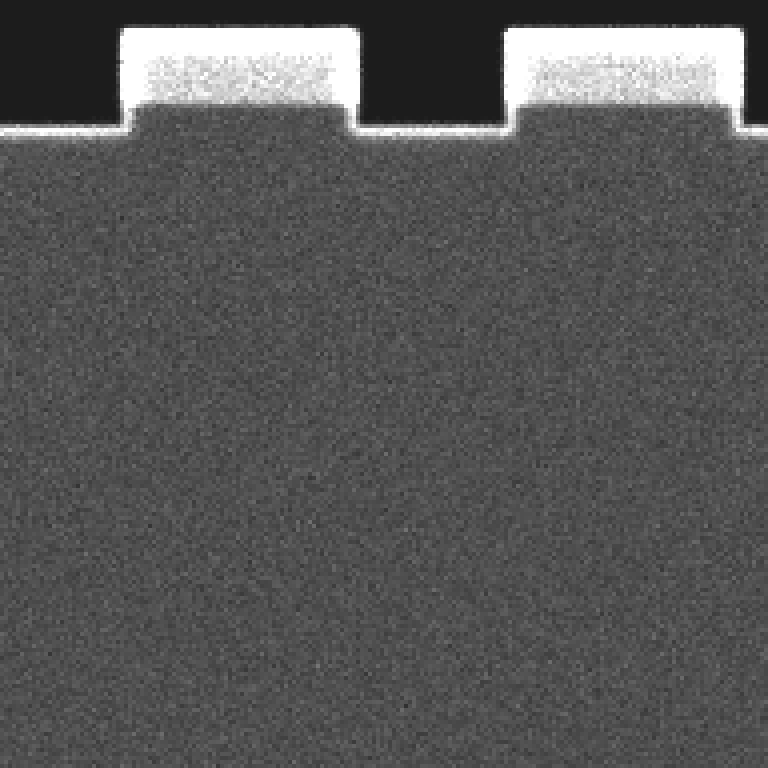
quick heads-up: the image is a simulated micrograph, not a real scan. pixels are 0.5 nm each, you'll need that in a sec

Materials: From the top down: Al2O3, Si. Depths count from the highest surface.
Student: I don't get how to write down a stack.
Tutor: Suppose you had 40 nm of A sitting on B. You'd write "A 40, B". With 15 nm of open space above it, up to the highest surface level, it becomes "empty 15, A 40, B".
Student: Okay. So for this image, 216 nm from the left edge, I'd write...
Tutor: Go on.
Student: empty 48, Si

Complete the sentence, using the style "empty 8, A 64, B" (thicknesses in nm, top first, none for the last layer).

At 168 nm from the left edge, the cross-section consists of Al2O3 36, Si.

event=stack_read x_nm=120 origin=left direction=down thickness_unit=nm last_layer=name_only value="Al2O3 36, Si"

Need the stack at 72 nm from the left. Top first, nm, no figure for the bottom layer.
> Al2O3 36, Si